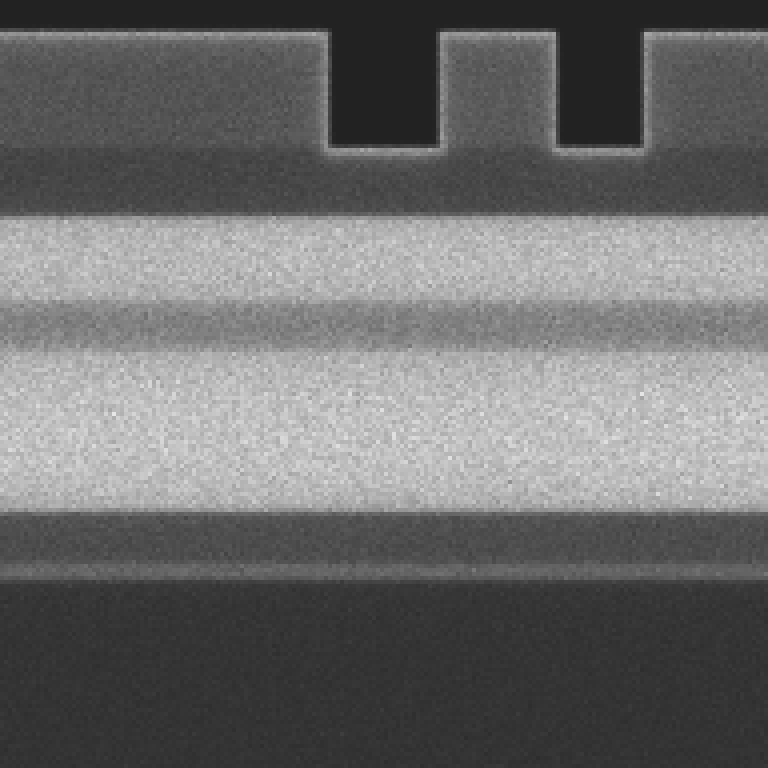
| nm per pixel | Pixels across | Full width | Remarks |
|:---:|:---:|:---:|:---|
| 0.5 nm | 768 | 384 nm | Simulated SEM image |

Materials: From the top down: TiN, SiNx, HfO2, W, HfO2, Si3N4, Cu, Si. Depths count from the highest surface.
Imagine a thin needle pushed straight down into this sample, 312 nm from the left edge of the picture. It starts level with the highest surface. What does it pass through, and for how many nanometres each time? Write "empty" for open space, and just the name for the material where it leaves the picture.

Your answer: empty 58, SiNx 34, HfO2 42, W 26, HfO2 80, Si3N4 26, Cu 8, Si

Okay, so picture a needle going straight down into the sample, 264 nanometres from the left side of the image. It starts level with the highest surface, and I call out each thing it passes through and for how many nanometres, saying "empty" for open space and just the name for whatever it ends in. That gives TiN 58, SiNx 34, HfO2 42, W 26, HfO2 80, Si3N4 26, Cu 8, Si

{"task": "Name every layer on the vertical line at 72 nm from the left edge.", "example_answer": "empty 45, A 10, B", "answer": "TiN 58, SiNx 34, HfO2 42, W 26, HfO2 80, Si3N4 26, Cu 8, Si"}